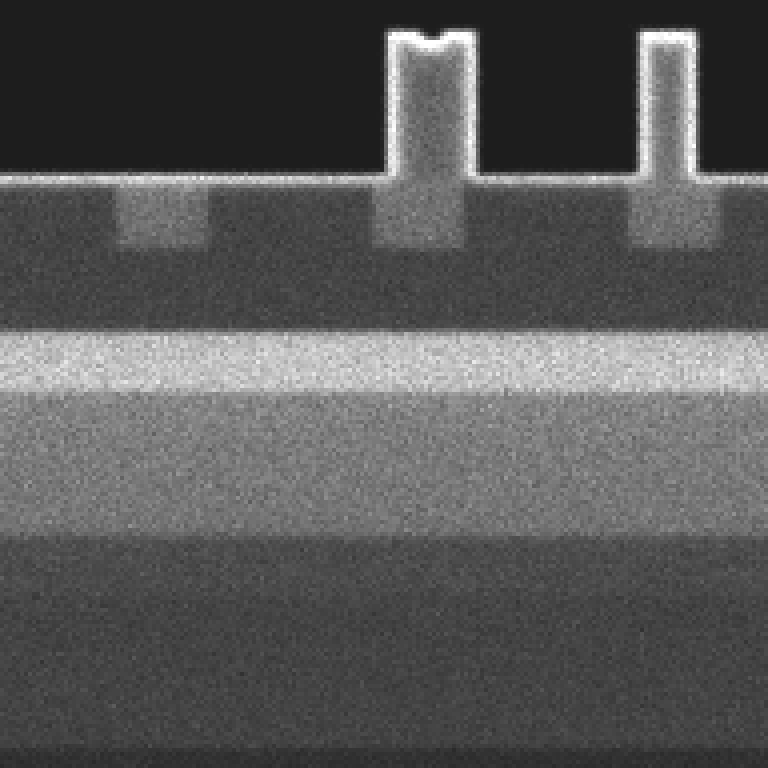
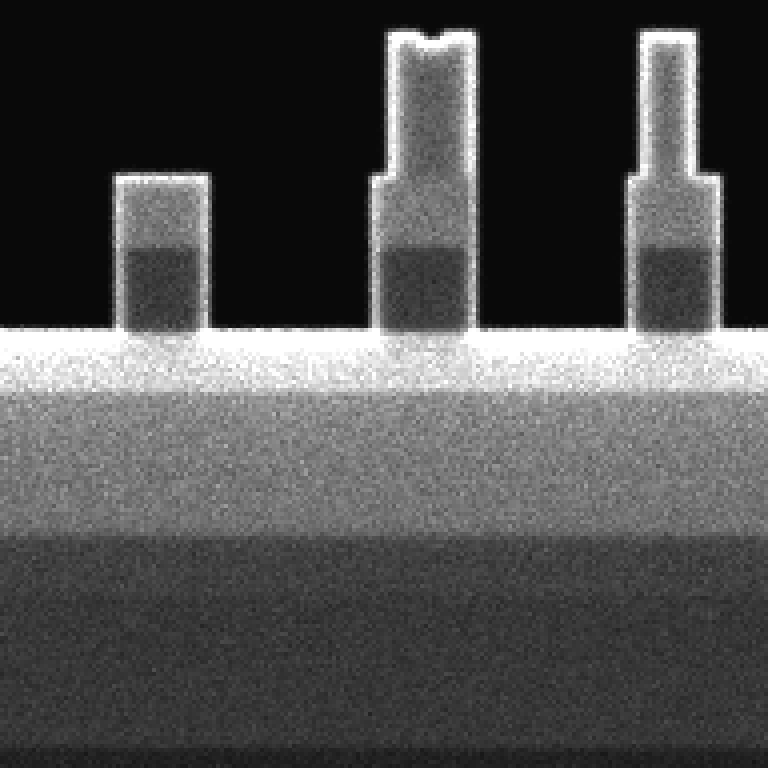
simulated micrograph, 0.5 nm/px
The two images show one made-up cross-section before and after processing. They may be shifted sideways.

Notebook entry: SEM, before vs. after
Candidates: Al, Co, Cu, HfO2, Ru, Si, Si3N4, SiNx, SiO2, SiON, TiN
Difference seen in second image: SiNx removed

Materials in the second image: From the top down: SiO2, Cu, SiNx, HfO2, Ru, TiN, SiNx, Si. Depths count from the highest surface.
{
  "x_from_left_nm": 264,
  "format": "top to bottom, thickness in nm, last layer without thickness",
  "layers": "empty 150, HfO2 30, Ru 72, TiN 30, SiNx 76, Si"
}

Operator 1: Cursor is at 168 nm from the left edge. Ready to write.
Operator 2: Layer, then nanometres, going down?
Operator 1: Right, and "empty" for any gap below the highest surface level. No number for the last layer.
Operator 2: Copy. empty 150, HfO2 30, Ru 72, TiN 30, SiNx 76, Si